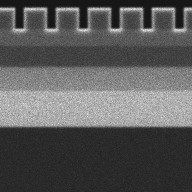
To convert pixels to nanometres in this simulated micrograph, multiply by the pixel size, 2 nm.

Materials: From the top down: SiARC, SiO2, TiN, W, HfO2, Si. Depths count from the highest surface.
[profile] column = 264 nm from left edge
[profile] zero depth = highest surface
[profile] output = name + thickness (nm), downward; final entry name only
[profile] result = SiARC 42, SiO2 34, TiN 42, W 48, HfO2 72, Si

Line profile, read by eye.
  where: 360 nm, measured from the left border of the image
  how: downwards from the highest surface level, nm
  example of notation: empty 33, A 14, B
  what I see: empty 42, SiO2 34, TiN 42, W 48, HfO2 72, Si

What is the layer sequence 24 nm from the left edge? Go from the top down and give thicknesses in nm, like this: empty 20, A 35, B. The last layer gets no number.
SiARC 42, SiO2 34, TiN 42, W 48, HfO2 72, Si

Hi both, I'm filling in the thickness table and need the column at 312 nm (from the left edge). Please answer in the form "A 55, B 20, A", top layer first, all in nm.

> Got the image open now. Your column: SiARC 42, SiO2 34, TiN 42, W 48, HfO2 72, Si